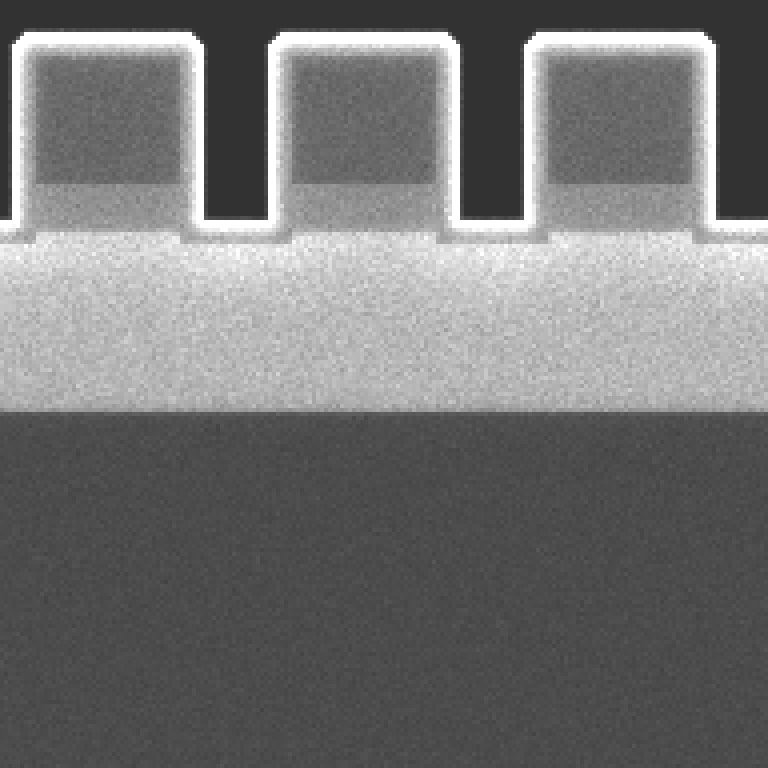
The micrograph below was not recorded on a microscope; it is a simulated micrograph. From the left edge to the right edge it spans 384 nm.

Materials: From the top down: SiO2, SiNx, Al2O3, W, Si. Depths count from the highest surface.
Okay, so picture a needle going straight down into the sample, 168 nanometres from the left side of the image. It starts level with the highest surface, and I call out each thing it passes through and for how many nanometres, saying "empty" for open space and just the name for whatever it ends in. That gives SiO2 12, SiNx 64, Al2O3 24, W 90, Si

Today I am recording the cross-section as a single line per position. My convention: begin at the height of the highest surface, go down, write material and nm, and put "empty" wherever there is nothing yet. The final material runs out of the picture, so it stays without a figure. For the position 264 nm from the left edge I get empty 4, SiO2 102, W 84, Si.